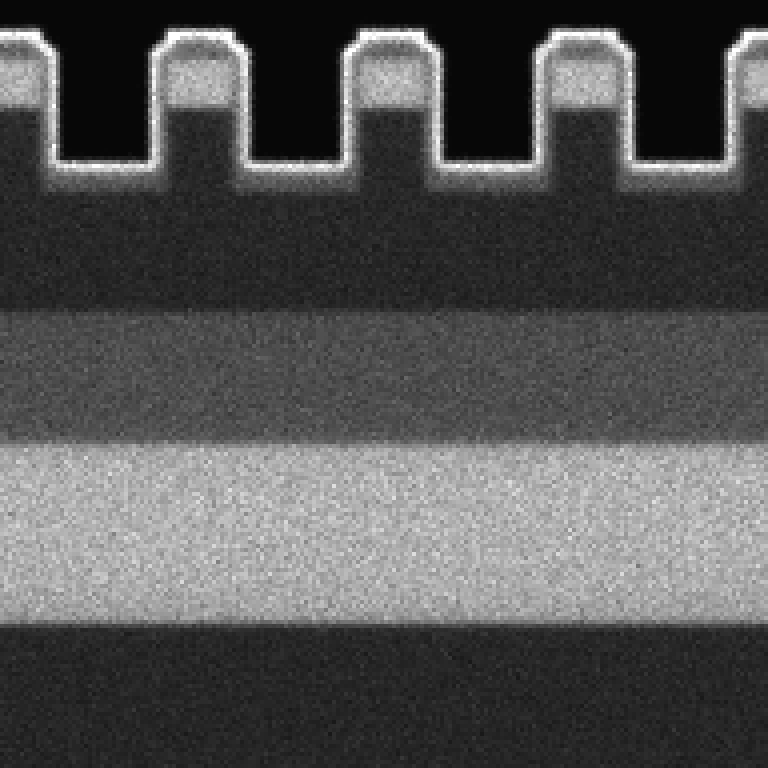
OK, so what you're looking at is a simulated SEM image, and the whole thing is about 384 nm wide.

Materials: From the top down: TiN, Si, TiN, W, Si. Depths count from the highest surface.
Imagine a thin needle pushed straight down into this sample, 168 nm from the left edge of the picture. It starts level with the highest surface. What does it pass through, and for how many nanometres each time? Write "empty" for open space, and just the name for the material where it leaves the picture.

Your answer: empty 66, TiN 14, Si 60, TiN 66, W 90, Si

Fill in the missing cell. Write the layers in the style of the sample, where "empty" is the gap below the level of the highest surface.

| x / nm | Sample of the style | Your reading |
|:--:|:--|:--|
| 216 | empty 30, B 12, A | empty 8, TiN 72, Si 60, TiN 66, W 90, Si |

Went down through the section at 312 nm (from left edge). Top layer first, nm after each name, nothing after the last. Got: empty 8, TiN 72, Si 60, TiN 66, W 90, Si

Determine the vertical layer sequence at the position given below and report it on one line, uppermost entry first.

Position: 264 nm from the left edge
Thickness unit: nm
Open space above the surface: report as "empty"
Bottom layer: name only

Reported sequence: empty 66, TiN 14, Si 60, TiN 66, W 90, Si